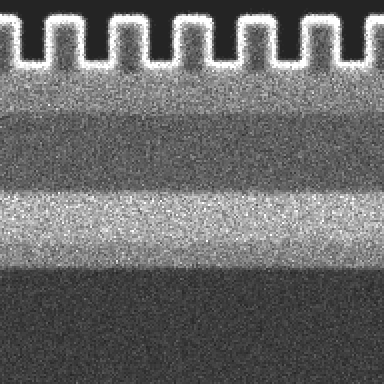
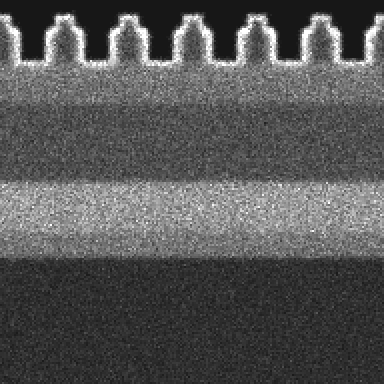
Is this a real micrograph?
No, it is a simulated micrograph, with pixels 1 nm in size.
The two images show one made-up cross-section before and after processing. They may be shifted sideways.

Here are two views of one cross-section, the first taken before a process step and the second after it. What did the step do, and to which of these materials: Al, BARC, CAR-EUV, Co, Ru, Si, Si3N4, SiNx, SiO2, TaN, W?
It removed SiO2.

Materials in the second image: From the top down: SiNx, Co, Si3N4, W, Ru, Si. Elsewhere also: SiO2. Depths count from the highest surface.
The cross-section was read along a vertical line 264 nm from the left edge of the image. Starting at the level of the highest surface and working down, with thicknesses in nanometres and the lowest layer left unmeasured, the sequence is SiNx 46, Co 42, Si3N4 78, W 50, Ru 26, Si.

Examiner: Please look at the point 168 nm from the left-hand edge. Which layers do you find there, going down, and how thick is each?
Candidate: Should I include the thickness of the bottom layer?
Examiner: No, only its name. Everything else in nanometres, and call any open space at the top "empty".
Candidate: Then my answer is empty 46, Co 42, Si3N4 78, W 50, Ru 26, Si